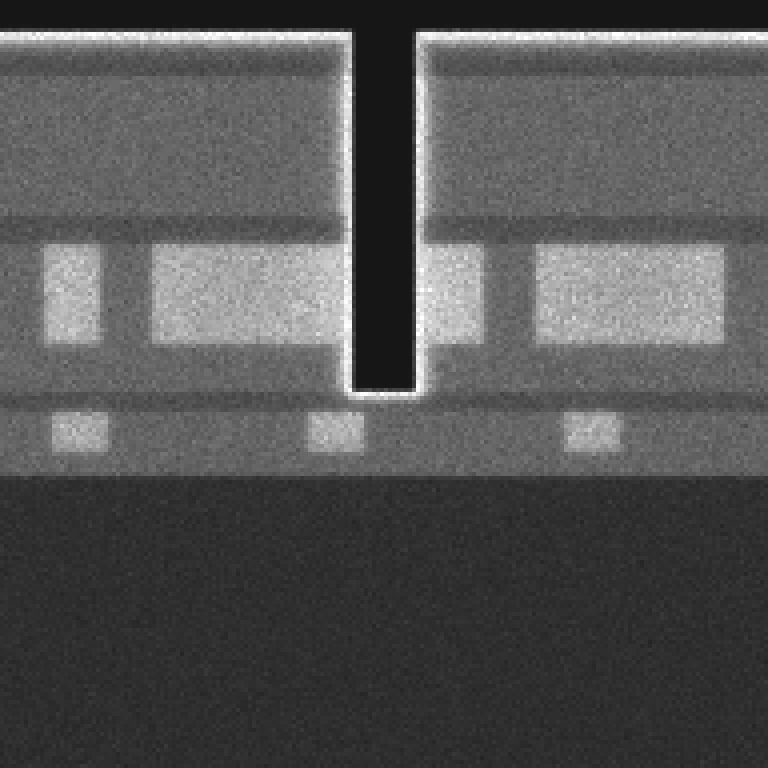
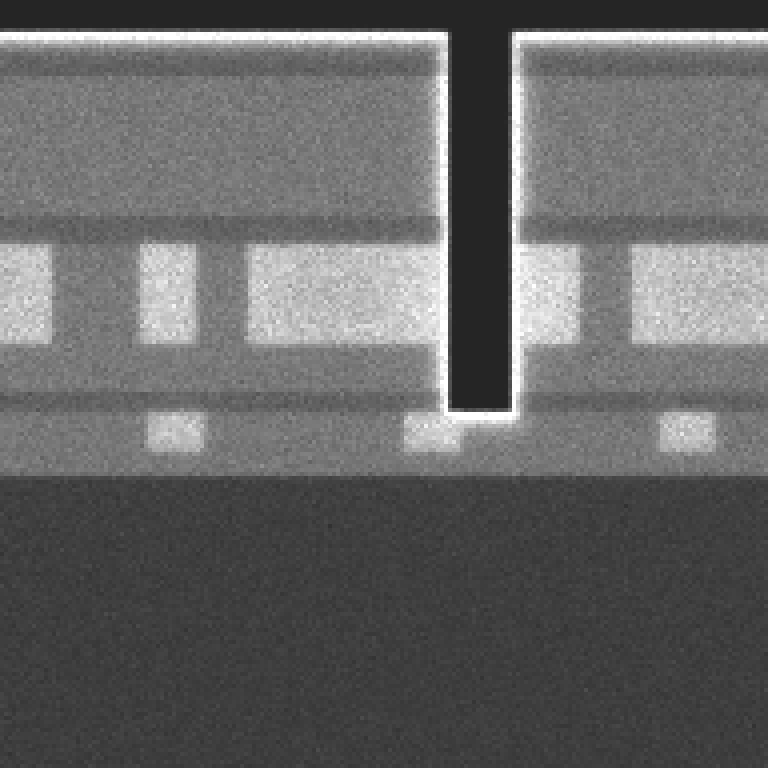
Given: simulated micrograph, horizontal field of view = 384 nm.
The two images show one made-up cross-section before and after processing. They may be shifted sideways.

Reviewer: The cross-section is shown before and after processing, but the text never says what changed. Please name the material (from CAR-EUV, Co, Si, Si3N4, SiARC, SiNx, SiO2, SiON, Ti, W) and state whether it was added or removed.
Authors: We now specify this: Si3N4, removed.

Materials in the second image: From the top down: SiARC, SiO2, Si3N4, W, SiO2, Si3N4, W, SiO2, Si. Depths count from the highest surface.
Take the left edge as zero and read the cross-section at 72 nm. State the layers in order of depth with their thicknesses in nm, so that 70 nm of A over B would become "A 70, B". SiARC 22, SiO2 70, Si3N4 14, W 50, SiO2 24, Si3N4 10, SiO2 32, Si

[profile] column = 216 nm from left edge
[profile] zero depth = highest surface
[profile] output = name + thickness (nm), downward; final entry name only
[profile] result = SiARC 22, SiO2 70, Si3N4 14, W 50, SiO2 24, Si3N4 10, W 20, SiO2 12, Si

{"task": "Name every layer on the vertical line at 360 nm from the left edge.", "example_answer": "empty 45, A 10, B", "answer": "SiARC 22, SiO2 70, Si3N4 14, W 50, SiO2 24, Si3N4 10, SiO2 32, Si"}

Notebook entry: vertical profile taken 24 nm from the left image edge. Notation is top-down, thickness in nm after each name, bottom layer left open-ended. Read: SiARC 22, SiO2 70, Si3N4 14, W 50, SiO2 24, Si3N4 10, SiO2 32, Si